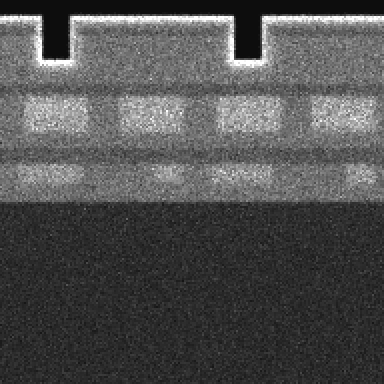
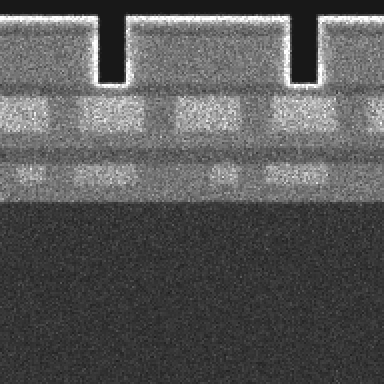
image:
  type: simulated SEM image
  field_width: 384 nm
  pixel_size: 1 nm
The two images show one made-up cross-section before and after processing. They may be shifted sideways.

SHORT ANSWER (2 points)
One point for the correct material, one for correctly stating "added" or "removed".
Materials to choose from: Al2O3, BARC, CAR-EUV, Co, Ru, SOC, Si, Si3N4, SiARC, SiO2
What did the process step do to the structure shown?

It removed SiO2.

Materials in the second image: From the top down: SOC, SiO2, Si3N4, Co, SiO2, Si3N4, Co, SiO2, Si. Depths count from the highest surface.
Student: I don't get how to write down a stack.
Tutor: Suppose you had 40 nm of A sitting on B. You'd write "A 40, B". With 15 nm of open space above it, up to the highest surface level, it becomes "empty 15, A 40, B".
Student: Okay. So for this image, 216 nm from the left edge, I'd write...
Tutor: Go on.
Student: SOC 20, SiO2 48, Si3N4 12, Co 36, SiO2 16, Si3N4 16, Co 20, SiO2 18, Si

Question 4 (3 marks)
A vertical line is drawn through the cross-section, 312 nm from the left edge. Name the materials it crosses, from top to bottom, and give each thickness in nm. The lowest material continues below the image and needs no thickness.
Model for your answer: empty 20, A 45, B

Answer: empty 68, Si3N4 12, Co 36, SiO2 16, Si3N4 16, Co 20, SiO2 18, Si